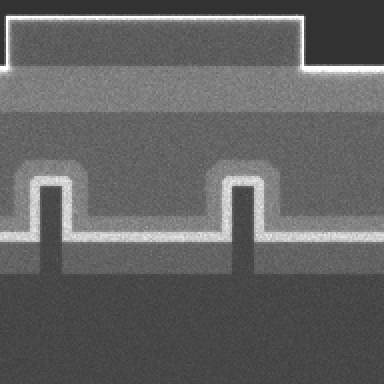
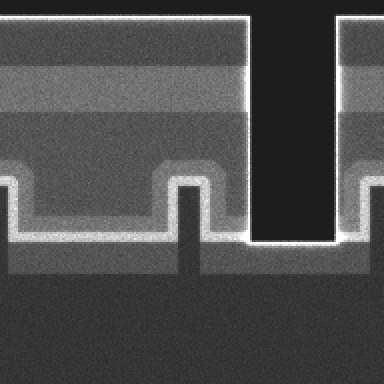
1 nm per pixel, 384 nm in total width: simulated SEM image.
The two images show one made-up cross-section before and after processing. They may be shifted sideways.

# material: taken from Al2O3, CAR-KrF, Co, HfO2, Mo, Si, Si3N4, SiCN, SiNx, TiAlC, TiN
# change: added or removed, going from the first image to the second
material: Al2O3 and Co and HfO2 and TiN
change: removed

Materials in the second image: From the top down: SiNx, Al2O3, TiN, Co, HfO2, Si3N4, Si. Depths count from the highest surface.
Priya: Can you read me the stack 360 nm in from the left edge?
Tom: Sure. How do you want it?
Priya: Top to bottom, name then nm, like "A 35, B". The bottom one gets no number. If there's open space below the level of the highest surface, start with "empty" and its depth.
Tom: SiNx 50, Al2O3 46, TiN 48, Co 20, HfO2 62, Si3N4 32, Si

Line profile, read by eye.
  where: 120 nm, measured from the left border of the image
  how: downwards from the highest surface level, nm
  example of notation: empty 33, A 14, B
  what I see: SiNx 50, Al2O3 46, TiN 104, Co 16, HfO2 10, Si3N4 32, Si